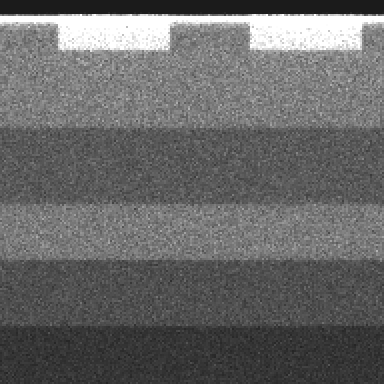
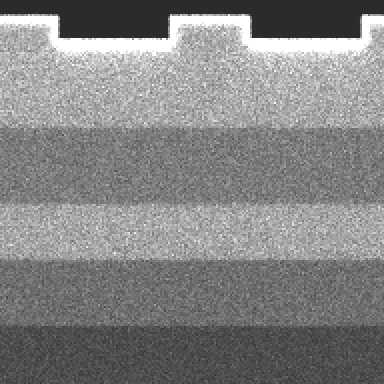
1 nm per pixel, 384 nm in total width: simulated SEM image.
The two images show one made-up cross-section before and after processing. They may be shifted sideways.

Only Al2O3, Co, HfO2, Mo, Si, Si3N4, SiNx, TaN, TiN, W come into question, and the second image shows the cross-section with HfO2 removed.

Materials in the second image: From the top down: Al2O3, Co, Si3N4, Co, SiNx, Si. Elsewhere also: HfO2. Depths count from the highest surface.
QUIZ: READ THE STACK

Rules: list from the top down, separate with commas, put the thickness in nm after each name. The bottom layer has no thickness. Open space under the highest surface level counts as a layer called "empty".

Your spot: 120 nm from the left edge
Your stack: empty 24, HfO2 10, Co 78, Si3N4 76, Co 56, SiNx 66, Si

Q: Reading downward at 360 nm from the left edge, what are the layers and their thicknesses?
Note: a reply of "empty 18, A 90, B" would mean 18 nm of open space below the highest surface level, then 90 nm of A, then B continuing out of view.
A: empty 24, HfO2 10, Co 78, Si3N4 76, Co 56, SiNx 66, Si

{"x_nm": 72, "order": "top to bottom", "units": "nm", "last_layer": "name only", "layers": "empty 24, HfO2 10, Co 78, Si3N4 76, Co 56, SiNx 66, Si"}